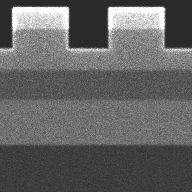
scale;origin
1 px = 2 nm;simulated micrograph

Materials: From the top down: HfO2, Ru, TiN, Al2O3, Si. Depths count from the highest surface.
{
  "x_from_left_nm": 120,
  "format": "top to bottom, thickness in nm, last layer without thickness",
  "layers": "HfO2 42, Ru 82, TiN 60, Al2O3 90, Si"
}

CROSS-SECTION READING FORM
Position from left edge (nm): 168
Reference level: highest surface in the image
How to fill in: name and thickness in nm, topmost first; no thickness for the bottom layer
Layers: empty 82, Ru 42, TiN 60, Al2O3 90, Si